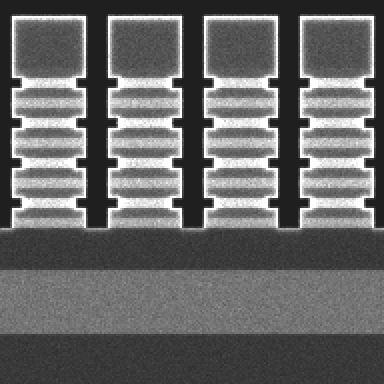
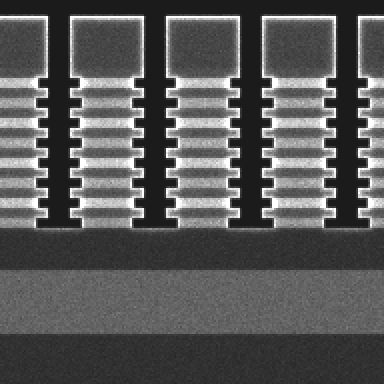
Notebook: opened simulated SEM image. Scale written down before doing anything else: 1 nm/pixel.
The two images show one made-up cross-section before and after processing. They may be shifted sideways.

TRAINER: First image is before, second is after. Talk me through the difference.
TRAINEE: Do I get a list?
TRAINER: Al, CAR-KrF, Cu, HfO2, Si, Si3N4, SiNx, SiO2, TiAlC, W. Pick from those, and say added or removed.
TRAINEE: removed: W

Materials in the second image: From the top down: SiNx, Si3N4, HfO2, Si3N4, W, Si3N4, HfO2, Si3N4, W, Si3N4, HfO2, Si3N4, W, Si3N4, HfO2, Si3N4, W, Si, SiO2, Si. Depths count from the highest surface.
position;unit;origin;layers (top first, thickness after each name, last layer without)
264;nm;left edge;SiNx 52, Si3N4 10, empty 10, Si3N4 10, empty 10, Si3N4 10, empty 10, Si3N4 10, empty 10, Si3N4 10, empty 10, Si3N4 10, empty 10, Si3N4 10, empty 10, Si3N4 10, empty 10, Si 42, SiO2 64, Si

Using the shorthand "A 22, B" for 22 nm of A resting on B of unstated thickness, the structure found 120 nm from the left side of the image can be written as SiNx 52, Si3N4 10, HfO2 10, Si3N4 10, W 10, Si3N4 10, HfO2 10, Si3N4 10, W 10, Si3N4 10, HfO2 10, Si3N4 10, W 10, Si3N4 10, HfO2 10, Si3N4 10, W 10, Si 42, SiO2 64, Si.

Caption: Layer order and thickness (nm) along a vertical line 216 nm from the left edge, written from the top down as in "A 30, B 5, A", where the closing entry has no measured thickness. SiNx 52, Si3N4 10, HfO2 10, Si3N4 10, W 10, Si3N4 10, HfO2 10, Si3N4 10, W 10, Si3N4 10, HfO2 10, Si3N4 10, W 10, Si3N4 10, HfO2 10, Si3N4 10, W 10, Si 42, SiO2 64, Si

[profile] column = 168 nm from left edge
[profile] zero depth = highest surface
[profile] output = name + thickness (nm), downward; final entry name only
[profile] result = SiNx 52, Si3N4 10, empty 10, Si3N4 10, empty 10, Si3N4 10, empty 10, Si3N4 10, empty 10, Si3N4 10, empty 10, Si3N4 10, empty 10, Si3N4 10, empty 10, Si3N4 10, empty 10, Si 42, SiO2 64, Si